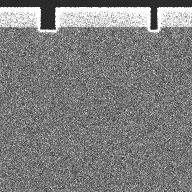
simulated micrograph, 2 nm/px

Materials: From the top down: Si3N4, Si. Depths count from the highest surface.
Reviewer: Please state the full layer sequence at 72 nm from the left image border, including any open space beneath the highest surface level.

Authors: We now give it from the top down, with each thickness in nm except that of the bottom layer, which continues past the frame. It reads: Si3N4 38, Si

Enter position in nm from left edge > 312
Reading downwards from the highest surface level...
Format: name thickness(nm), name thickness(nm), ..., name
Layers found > empty 44, Si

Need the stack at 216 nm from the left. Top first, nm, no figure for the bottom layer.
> Si3N4 38, Si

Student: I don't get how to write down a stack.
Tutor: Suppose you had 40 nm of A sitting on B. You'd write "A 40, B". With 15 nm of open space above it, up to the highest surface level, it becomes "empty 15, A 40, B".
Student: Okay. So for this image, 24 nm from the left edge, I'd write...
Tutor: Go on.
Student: Si3N4 38, Si